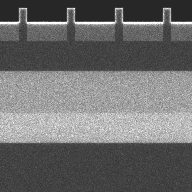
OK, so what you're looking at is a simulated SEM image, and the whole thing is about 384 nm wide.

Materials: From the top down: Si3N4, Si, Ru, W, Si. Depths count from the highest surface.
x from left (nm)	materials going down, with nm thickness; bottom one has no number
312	empty 28, Si3N4 38, Si 60, Ru 84, W 60, Si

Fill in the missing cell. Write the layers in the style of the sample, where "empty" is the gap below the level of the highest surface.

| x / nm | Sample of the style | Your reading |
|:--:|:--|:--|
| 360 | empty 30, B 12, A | empty 28, Si3N4 38, Si 60, Ru 84, W 60, Si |